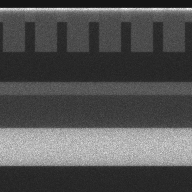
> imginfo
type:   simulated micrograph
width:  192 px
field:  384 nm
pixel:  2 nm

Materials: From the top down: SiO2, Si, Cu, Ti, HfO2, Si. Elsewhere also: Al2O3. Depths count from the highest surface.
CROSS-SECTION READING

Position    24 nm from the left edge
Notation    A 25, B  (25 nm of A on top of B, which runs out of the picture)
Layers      SiO2 88, Si 60, Cu 26, Ti 66, HfO2 76, Si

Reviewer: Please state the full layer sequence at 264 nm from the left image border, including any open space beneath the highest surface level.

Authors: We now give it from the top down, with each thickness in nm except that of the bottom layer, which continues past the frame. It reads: SiO2 88, Si 60, Cu 26, Ti 66, HfO2 76, Si